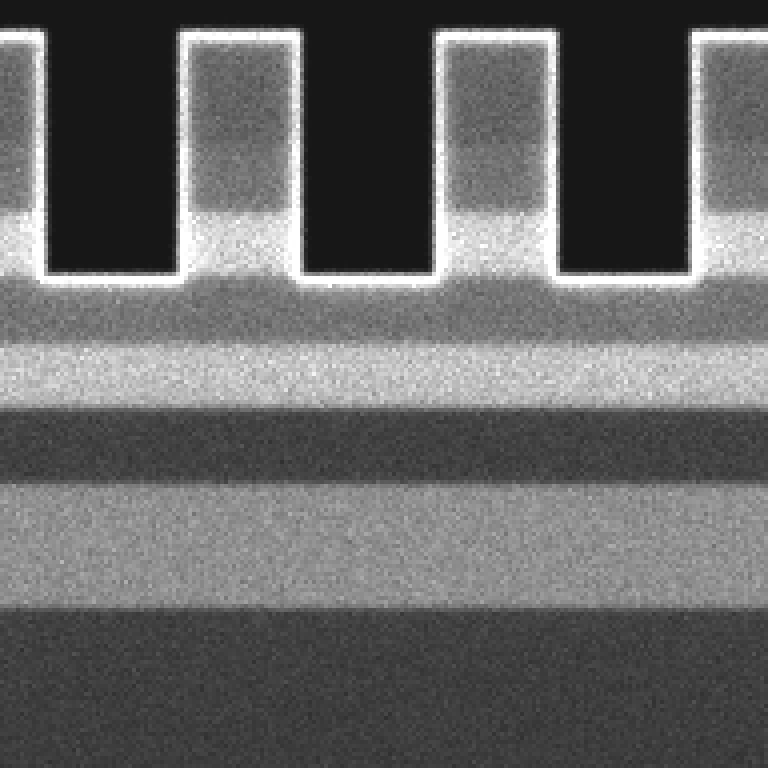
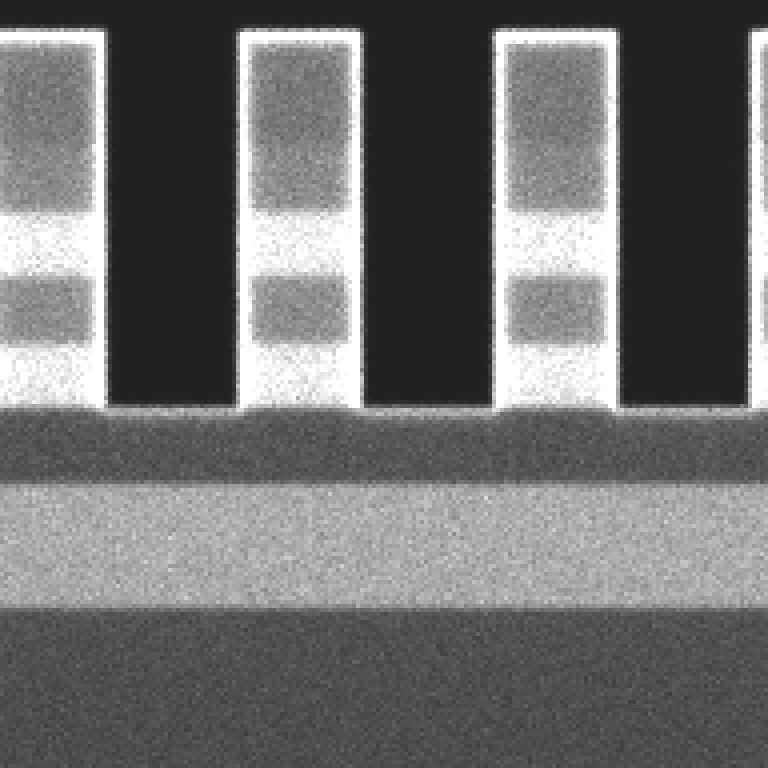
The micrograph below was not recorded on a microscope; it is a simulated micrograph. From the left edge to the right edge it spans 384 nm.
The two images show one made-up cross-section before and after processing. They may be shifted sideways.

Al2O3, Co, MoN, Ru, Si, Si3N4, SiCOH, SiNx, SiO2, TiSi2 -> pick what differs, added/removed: Co and Si3N4 removed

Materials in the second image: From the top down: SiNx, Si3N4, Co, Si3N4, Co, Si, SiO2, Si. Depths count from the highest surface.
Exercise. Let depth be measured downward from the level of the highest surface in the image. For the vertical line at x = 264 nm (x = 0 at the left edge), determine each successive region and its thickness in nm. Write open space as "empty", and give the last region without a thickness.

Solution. SiNx 56, Si3N4 34, Co 32, Si3N4 34, Co 32, Si 38, SiO2 62, Si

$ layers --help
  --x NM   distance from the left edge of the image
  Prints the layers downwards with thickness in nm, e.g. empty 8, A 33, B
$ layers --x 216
empty 188, Si 38, SiO2 62, Si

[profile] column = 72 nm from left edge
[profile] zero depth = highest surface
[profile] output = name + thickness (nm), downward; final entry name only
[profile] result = empty 188, Si 38, SiO2 62, Si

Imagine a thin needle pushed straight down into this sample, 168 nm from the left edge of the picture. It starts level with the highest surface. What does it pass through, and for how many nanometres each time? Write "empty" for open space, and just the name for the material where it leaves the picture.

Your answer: SiNx 56, Si3N4 34, Co 32, Si3N4 34, Co 32, Si 38, SiO2 62, Si